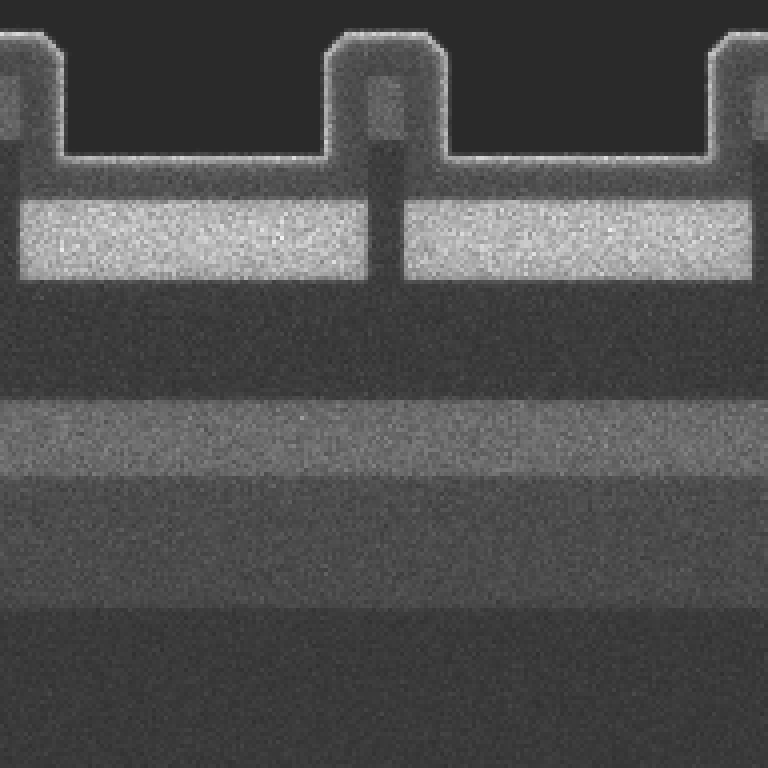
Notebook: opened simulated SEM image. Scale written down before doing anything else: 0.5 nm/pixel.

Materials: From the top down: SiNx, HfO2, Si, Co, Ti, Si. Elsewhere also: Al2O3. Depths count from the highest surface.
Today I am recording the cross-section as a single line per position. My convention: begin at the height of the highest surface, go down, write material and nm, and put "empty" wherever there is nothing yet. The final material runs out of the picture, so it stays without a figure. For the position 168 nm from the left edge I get empty 4, SiNx 80, HfO2 40, Si 60, Co 38, Ti 66, Si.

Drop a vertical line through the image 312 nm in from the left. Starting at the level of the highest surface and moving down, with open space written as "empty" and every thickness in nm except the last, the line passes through empty 62, SiNx 22, HfO2 40, Si 60, Co 38, Ti 66, Si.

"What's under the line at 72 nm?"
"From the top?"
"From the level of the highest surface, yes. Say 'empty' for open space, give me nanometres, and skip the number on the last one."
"empty 62, SiNx 22, HfO2 40, Si 60, Co 38, Ti 66, Si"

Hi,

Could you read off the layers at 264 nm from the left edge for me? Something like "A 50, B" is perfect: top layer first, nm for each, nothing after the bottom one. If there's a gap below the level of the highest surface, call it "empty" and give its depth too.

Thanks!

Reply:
empty 62, SiNx 22, HfO2 40, Si 60, Co 38, Ti 66, Si